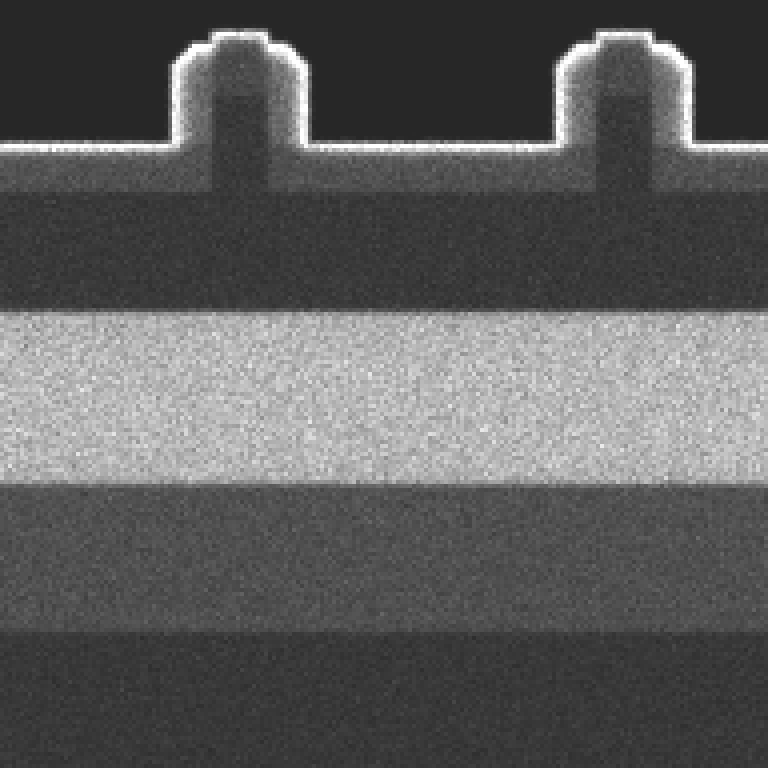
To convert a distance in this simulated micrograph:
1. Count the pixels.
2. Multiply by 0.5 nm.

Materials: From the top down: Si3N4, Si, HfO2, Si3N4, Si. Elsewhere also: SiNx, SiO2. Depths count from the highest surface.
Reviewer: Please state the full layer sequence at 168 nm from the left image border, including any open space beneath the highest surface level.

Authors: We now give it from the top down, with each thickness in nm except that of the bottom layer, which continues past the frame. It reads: empty 56, Si3N4 24, Si 60, HfO2 86, Si3N4 74, Si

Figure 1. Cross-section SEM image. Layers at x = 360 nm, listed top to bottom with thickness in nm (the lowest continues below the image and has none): empty 56, Si3N4 24, Si 60, HfO2 86, Si3N4 74, Si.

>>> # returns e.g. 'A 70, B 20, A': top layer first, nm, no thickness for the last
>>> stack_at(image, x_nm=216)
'empty 56, Si3N4 24, Si 60, HfO2 86, Si3N4 74, Si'